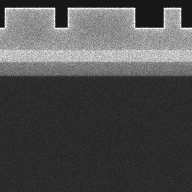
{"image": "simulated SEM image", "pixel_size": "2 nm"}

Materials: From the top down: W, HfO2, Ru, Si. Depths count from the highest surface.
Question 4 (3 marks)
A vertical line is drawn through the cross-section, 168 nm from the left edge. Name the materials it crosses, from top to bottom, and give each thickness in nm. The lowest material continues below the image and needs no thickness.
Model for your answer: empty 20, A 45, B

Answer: W 84, HfO2 24, Ru 28, Si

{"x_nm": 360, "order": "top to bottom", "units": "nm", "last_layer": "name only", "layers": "W 84, HfO2 24, Ru 28, Si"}